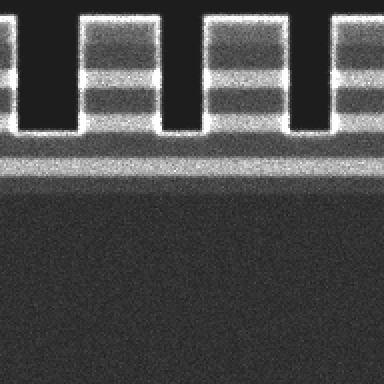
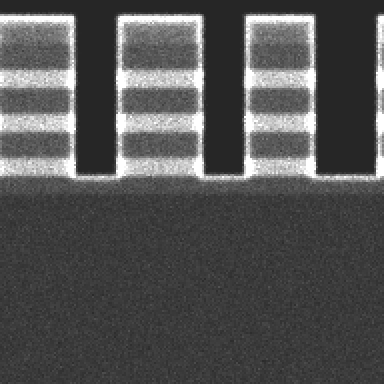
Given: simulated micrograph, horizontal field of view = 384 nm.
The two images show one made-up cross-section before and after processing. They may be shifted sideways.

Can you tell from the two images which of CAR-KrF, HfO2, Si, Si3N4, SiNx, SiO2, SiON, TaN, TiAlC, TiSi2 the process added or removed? Yes, it removed HfO2 and Si3N4.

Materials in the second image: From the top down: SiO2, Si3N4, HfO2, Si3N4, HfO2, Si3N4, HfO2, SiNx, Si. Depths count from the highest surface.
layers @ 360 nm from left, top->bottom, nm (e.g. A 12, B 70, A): empty 160, SiNx 18, Si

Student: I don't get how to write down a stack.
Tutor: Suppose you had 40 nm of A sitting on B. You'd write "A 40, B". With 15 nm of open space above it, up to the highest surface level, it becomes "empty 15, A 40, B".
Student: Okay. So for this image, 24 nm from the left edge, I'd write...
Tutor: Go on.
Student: SiO2 28, Si3N4 26, HfO2 18, Si3N4 26, HfO2 18, Si3N4 26, HfO2 18, SiNx 18, Si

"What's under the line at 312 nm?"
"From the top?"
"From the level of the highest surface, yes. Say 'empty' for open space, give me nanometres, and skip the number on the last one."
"SiO2 28, Si3N4 26, HfO2 18, Si3N4 26, HfO2 18, Si3N4 26, HfO2 18, SiNx 18, Si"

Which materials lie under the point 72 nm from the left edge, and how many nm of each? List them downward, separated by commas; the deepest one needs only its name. SiO2 28, Si3N4 26, HfO2 18, Si3N4 26, HfO2 18, Si3N4 26, HfO2 18, SiNx 18, Si